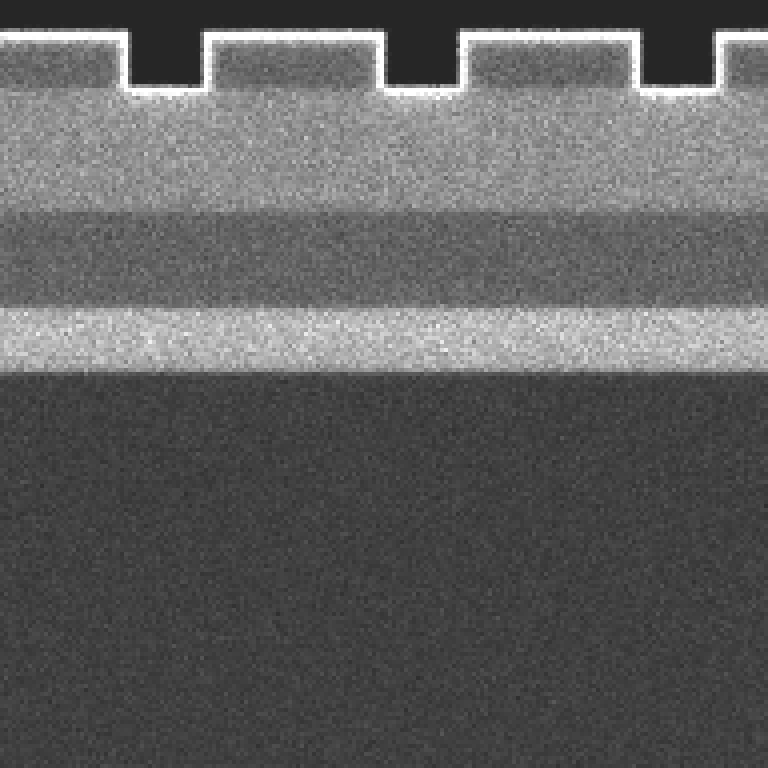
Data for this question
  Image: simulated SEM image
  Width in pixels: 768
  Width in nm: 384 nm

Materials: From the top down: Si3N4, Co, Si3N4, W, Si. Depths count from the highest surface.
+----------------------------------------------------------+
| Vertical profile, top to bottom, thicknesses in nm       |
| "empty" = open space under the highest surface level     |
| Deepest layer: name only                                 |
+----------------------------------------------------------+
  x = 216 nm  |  empty 28, Co 62, Si3N4 48, W 32, Si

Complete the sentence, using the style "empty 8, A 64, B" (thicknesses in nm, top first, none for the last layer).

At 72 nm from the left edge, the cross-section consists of empty 28, Co 62, Si3N4 48, W 32, Si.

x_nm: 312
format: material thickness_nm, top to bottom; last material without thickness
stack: Si3N4 28, Co 62, Si3N4 48, W 32, Si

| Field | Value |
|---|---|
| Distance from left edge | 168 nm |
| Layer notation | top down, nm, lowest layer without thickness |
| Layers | Si3N4 28, Co 62, Si3N4 48, W 32, Si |